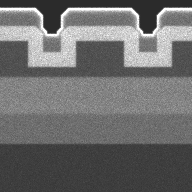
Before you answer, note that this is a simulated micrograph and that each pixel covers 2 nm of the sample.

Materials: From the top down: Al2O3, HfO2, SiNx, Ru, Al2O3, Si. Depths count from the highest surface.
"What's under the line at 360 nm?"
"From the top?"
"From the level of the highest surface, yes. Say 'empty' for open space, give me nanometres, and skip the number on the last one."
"Al2O3 36, HfO2 30, SiNx 72, Ru 74, Al2O3 60, Si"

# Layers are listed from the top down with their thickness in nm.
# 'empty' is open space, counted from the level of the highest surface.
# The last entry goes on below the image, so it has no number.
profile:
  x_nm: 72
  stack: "empty 2, Al2O3 36, HfO2 80, SiNx 20, Ru 74, Al2O3 60, Si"